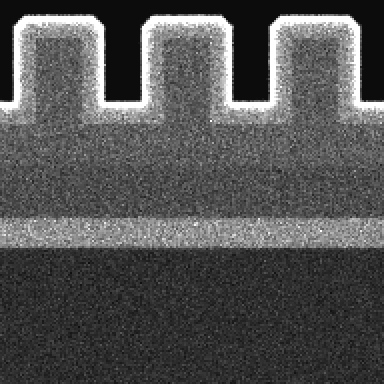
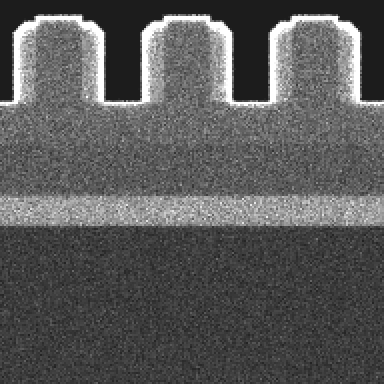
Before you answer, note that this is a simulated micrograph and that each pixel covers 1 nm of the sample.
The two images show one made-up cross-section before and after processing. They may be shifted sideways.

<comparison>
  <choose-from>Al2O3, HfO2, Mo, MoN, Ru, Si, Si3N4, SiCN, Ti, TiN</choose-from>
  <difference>Al2O3 removed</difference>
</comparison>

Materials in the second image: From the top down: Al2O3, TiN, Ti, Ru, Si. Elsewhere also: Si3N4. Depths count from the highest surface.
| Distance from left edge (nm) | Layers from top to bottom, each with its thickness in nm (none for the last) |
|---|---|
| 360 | empty 86, TiN 42, Ti 52, Ru 30, Si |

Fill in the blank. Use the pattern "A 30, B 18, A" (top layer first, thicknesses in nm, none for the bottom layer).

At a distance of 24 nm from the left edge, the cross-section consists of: empty 6, Al2O3 80, TiN 42, Ti 52, Ru 30, Si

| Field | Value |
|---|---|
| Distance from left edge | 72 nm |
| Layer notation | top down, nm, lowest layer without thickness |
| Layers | Si3N4 86, TiN 42, Ti 52, Ru 30, Si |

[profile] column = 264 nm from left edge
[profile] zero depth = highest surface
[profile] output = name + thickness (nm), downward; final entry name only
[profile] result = empty 86, TiN 42, Ti 52, Ru 30, Si